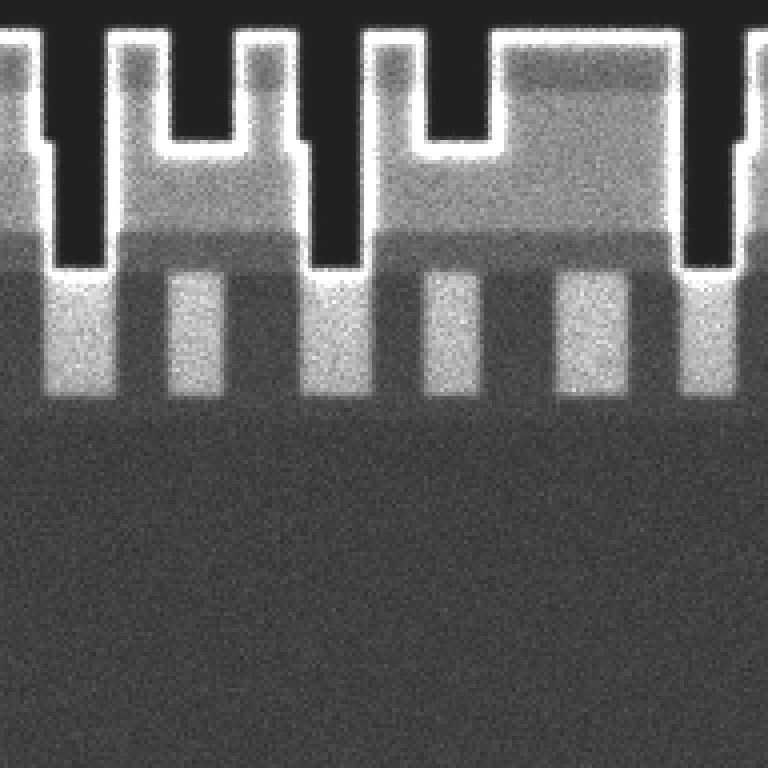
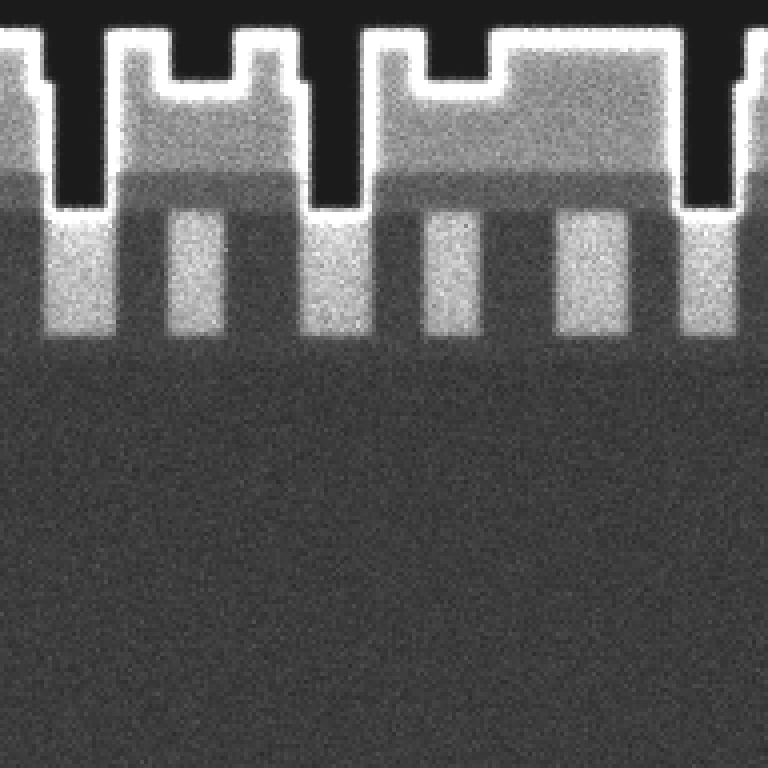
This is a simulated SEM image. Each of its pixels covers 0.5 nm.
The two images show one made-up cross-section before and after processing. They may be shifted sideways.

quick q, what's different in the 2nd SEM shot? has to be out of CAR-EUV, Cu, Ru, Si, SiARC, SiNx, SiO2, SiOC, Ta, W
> SiARC removed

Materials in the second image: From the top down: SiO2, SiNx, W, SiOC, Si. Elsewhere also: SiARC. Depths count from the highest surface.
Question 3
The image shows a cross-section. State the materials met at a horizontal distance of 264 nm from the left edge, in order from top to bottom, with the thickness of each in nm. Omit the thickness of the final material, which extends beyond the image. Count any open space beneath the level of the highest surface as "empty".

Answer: SiO2 70, SiNx 20, SiOC 74, Si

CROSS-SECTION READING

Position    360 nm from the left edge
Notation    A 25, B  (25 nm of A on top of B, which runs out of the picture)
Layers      empty 90, W 62, SiOC 12, Si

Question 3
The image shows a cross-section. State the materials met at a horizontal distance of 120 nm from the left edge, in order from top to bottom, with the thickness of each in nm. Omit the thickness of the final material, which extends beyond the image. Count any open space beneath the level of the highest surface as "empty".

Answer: SiO2 70, SiNx 20, SiOC 74, Si